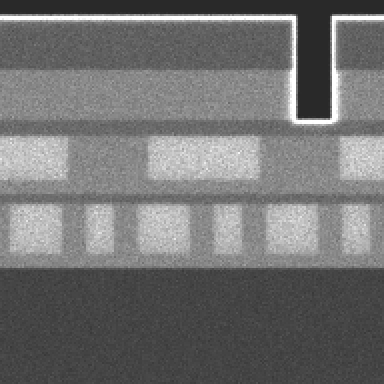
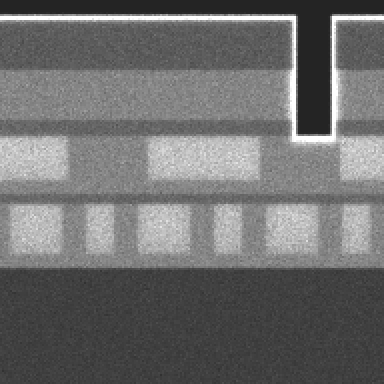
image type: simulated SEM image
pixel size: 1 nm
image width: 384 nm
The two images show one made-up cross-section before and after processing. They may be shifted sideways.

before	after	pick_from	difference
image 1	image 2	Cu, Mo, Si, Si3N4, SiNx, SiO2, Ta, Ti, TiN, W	Si3N4 removed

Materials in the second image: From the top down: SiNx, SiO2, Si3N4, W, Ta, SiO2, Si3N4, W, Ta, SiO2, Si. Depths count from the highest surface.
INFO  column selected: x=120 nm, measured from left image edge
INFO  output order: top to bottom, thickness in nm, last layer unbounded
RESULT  SiNx 54, SiO2 50, Si3N4 16, SiO2 58, Si3N4 10, SiO2 64, Si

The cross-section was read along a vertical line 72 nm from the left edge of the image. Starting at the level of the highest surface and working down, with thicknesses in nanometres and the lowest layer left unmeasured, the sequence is SiNx 54, SiO2 50, Si3N4 16, SiO2 58, Si3N4 10, SiO2 64, Si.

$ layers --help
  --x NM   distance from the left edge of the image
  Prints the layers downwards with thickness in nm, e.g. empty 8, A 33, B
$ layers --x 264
SiNx 54, SiO2 50, Si3N4 16, SiO2 58, Si3N4 10, SiO2 64, Si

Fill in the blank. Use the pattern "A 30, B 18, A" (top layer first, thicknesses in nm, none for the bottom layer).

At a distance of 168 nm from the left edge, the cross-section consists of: SiNx 54, SiO2 50, Si3N4 16, W 34, Ta 10, SiO2 14, Si3N4 10, W 40, Ta 10, SiO2 14, Si